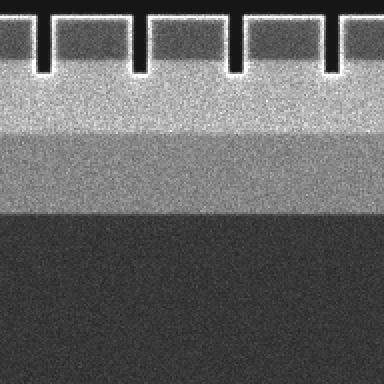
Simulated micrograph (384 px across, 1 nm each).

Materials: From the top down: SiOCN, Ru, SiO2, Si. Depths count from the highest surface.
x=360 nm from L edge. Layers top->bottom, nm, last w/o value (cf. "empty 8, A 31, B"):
SiOCN 44, Ru 74, SiO2 80, Si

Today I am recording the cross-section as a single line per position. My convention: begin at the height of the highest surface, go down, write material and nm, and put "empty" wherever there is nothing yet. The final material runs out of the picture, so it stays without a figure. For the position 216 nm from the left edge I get SiOCN 44, Ru 74, SiO2 80, Si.